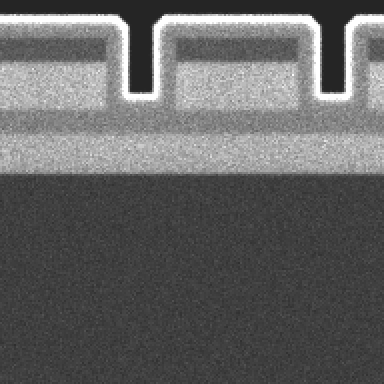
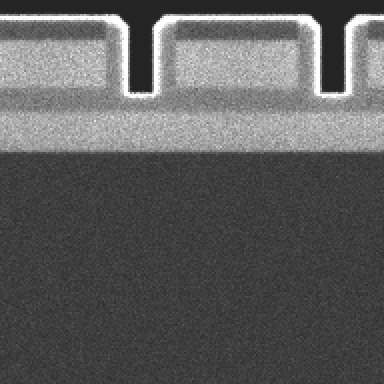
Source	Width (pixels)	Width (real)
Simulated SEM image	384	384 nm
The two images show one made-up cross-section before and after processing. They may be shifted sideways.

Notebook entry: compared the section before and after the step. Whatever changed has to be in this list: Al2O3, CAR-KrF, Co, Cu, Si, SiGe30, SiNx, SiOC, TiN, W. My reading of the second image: Al2O3 removed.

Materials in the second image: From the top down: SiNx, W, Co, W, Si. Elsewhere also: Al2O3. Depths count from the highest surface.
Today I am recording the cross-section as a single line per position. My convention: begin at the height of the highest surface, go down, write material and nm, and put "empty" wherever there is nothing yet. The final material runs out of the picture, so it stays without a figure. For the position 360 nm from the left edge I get Al2O3 78, Co 18, W 40, Si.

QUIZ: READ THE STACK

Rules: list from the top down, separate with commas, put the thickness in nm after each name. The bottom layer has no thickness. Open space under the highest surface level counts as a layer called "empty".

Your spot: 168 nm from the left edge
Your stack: Al2O3 78, Co 18, W 40, Si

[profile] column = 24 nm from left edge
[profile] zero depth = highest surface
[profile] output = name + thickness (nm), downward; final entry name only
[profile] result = SiNx 24, W 48, Co 24, W 40, Si